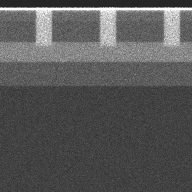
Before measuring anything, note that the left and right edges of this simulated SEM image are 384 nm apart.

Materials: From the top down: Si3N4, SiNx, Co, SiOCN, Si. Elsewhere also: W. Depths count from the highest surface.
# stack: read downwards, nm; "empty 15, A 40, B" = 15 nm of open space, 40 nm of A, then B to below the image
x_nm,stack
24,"Si3N4 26, SiNx 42, Co 40, SiOCN 48, Si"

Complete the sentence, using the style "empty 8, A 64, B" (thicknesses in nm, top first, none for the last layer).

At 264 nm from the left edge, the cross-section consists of Si3N4 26, SiNx 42, Co 40, SiOCN 48, Si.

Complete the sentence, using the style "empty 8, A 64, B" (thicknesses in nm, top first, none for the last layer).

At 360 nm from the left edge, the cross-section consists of Si3N4 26, SiNx 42, Co 40, SiOCN 48, Si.